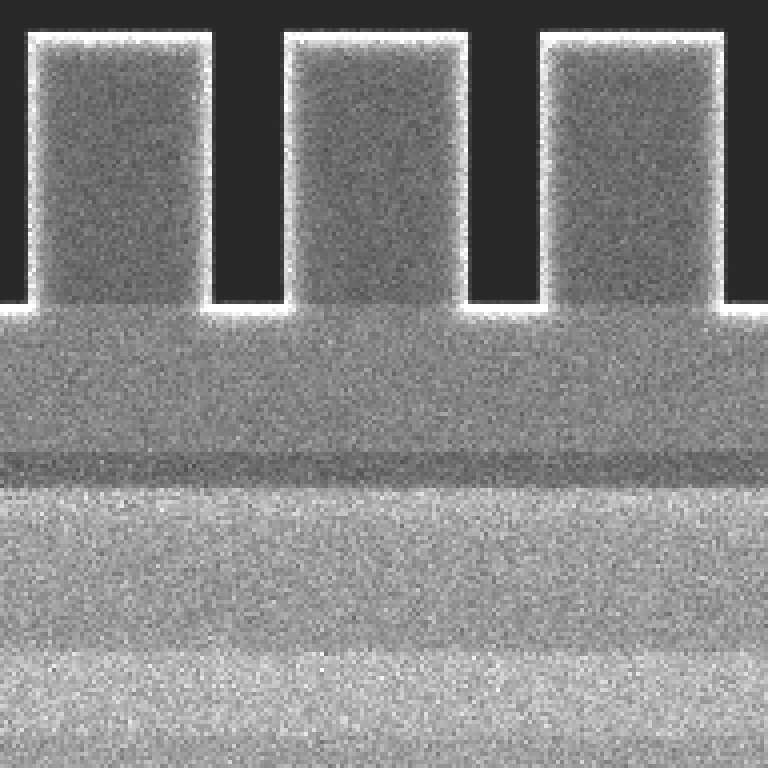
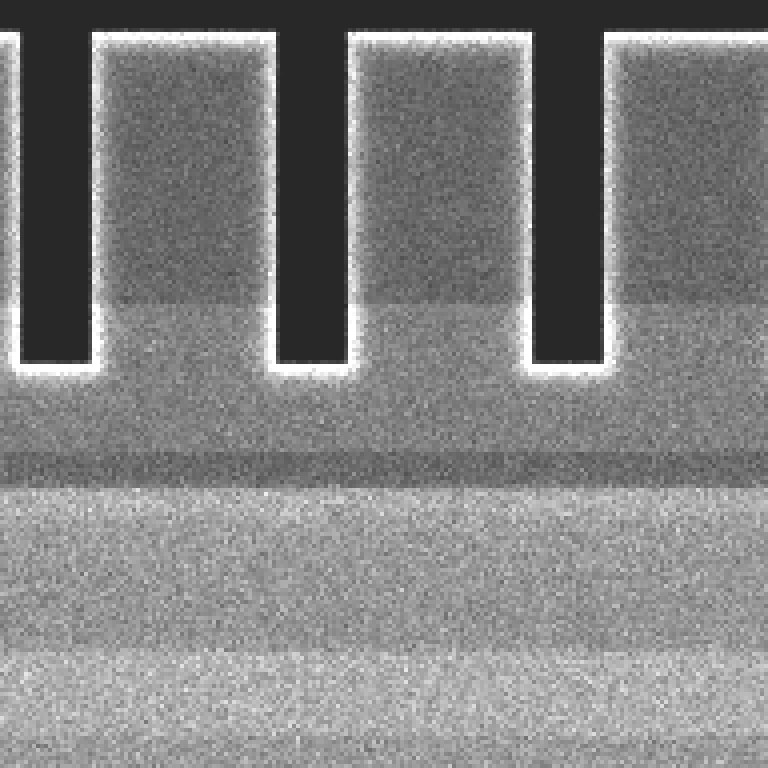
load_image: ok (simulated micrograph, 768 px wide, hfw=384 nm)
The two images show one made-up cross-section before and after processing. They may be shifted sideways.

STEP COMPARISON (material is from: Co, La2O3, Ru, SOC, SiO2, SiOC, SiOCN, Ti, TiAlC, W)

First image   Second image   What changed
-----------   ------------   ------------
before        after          SiO2, removed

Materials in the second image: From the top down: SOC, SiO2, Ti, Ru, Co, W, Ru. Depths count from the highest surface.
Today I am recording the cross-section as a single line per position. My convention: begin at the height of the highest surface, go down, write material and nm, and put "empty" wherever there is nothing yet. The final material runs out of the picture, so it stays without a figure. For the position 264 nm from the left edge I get SOC 136, SiO2 74, Ti 18, Ru 14, Co 68, W 42, Ru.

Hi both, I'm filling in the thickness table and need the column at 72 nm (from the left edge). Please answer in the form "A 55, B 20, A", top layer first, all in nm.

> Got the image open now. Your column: SOC 136, SiO2 74, Ti 18, Ru 14, Co 68, W 42, Ru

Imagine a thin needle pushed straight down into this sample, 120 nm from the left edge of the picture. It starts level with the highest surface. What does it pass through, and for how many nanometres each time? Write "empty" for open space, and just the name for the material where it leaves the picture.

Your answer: SOC 136, SiO2 74, Ti 18, Ru 14, Co 68, W 42, Ru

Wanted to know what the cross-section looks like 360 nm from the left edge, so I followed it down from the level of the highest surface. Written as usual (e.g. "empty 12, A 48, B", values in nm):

SOC 136, SiO2 74, Ti 18, Ru 14, Co 68, W 42, Ru